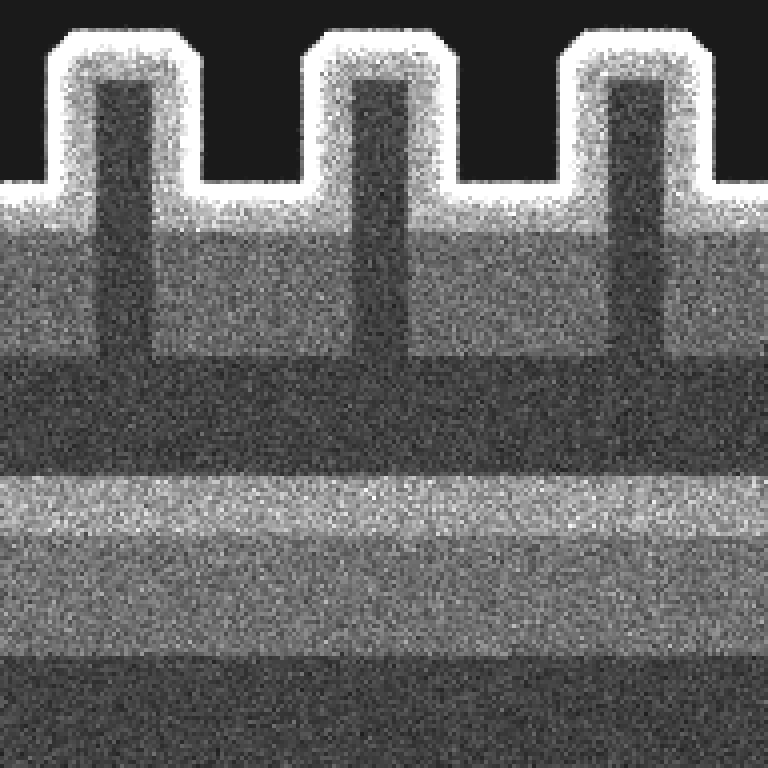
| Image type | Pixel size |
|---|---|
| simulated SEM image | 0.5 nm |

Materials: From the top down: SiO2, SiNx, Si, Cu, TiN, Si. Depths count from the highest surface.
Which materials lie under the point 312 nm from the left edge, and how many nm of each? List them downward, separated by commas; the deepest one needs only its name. SiO2 24, Si 198, Cu 30, TiN 60, Si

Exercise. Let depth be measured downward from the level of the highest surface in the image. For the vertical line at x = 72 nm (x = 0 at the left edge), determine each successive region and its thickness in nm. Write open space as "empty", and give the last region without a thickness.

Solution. SiO2 24, Si 198, Cu 30, TiN 60, Si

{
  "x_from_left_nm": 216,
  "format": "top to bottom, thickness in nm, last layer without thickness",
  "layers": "empty 2, SiO2 98, SiNx 62, Si 60, Cu 30, TiN 60, Si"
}